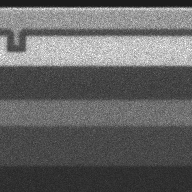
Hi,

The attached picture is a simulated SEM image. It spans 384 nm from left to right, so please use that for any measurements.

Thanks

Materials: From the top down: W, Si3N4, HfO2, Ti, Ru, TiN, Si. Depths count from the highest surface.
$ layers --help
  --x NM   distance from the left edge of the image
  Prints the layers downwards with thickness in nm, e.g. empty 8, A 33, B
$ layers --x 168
W 42, Si3N4 14, HfO2 60, Ti 68, Ru 52, TiN 80, Si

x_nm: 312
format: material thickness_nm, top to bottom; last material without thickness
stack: W 42, Si3N4 14, HfO2 60, Ti 68, Ru 52, TiN 80, Si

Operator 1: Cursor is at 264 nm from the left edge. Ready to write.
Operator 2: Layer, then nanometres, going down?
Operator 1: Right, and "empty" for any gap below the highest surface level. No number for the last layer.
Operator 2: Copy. W 42, Si3N4 14, HfO2 60, Ti 68, Ru 52, TiN 80, Si